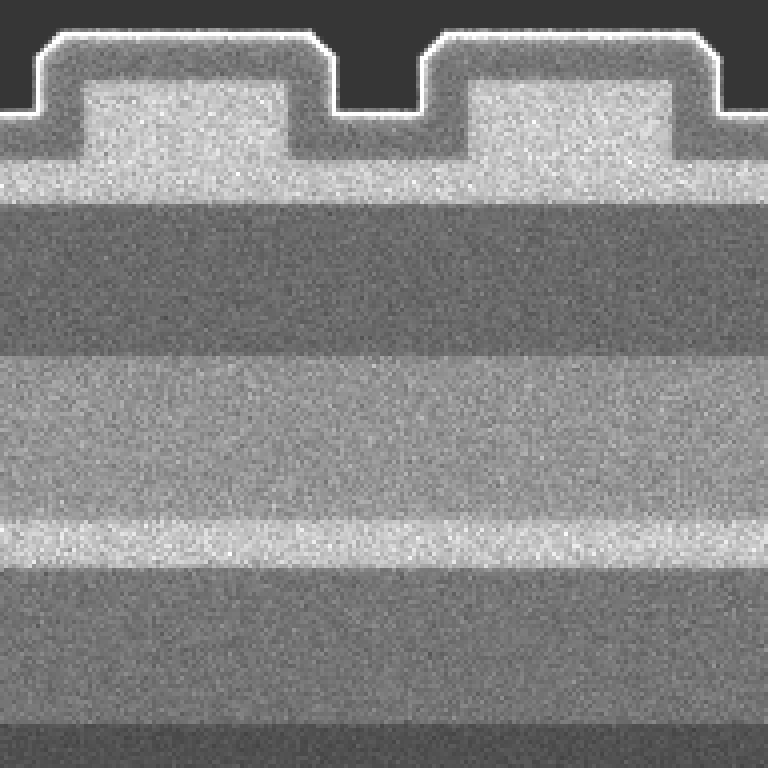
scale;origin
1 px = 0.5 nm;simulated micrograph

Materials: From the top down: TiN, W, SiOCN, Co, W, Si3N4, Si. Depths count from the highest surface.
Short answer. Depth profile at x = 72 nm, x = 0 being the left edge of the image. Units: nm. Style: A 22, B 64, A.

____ TiN 24, W 62, SiOCN 76, Co 82, W 24, Si3N4 78, Si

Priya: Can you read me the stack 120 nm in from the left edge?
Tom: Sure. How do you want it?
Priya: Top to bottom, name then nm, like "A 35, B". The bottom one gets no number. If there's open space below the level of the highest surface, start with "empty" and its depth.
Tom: TiN 24, W 62, SiOCN 76, Co 82, W 24, Si3N4 78, Si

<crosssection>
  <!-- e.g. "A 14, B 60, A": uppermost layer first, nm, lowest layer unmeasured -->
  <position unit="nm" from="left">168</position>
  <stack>empty 40, TiN 24, W 22, SiOCN 76, Co 82, W 24, Si3N4 78, Si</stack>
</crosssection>